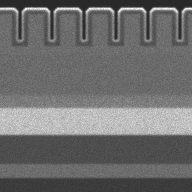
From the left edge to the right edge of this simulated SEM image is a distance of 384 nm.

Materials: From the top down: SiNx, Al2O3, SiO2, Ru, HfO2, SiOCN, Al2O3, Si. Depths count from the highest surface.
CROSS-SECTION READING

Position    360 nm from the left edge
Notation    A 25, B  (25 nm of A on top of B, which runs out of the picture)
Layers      empty 64, SiNx 12, Al2O3 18, SiO2 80, Ru 26, HfO2 54, SiOCN 58, Al2O3 28, Si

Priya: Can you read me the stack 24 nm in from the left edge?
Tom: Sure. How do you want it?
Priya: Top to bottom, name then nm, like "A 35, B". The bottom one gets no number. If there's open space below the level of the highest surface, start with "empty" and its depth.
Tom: SiNx 76, Al2O3 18, SiO2 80, Ru 26, HfO2 54, SiOCN 58, Al2O3 28, Si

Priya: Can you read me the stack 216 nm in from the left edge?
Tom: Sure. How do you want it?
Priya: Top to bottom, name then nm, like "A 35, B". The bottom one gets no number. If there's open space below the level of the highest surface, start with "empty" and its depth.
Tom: SiNx 76, Al2O3 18, SiO2 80, Ru 26, HfO2 54, SiOCN 58, Al2O3 28, Si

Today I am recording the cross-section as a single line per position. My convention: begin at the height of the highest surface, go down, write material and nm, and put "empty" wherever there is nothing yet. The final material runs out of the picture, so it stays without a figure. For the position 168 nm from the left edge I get empty 64, SiNx 12, Al2O3 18, SiO2 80, Ru 26, HfO2 54, SiOCN 58, Al2O3 28, Si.